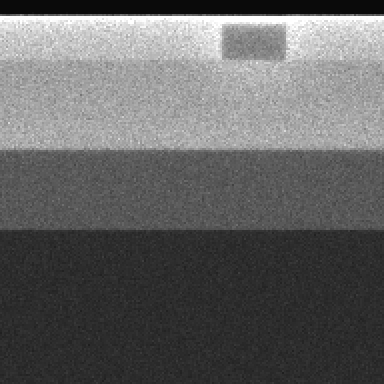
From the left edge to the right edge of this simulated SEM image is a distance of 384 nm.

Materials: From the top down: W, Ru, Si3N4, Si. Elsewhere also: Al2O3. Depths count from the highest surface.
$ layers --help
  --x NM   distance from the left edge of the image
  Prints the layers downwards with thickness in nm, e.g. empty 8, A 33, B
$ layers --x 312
W 44, Ru 90, Si3N4 80, Si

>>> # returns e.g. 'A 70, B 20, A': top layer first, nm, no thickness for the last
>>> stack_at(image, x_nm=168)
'W 44, Ru 90, Si3N4 80, Si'